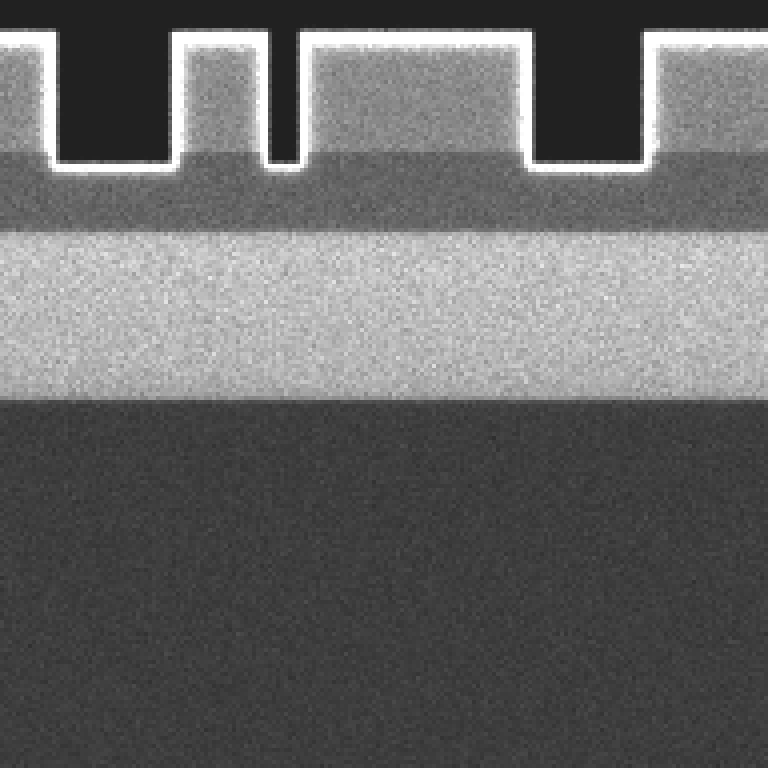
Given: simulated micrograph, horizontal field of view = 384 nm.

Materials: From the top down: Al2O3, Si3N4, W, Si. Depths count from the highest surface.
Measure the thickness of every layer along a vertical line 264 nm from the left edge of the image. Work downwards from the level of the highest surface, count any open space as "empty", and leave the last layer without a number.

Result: Al2O3 60, Si3N4 40, W 84, Si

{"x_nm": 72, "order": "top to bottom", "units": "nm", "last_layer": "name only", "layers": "empty 66, Si3N4 34, W 84, Si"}